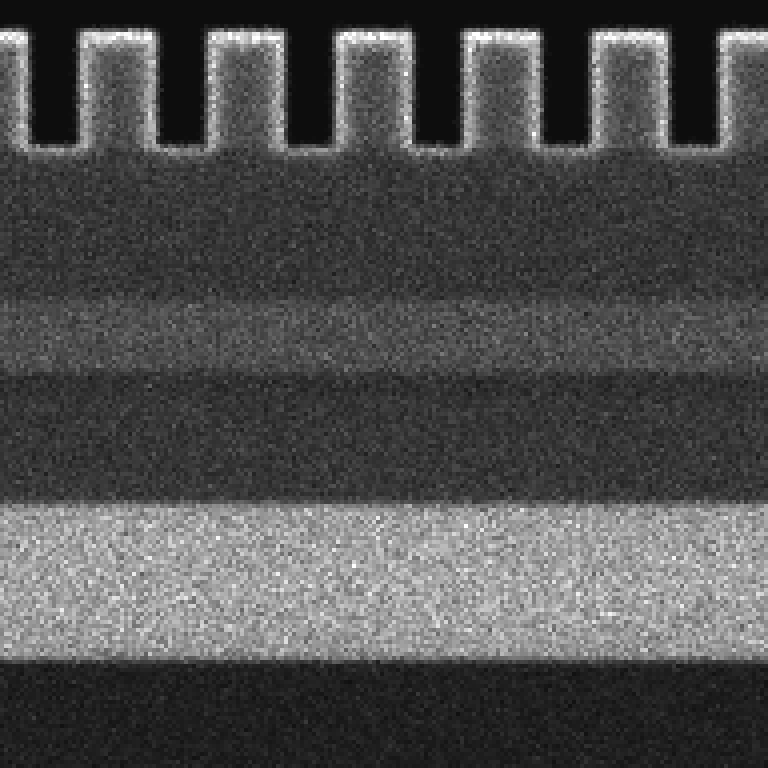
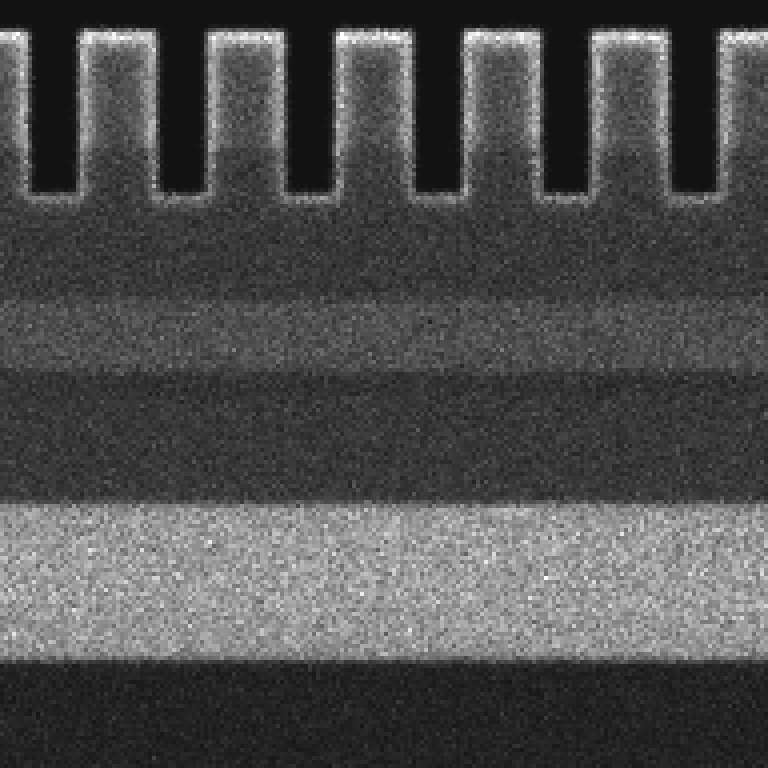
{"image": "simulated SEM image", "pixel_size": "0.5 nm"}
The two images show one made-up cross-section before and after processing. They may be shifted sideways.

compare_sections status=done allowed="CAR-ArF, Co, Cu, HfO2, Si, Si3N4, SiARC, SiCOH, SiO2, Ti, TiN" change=removed material="TiN"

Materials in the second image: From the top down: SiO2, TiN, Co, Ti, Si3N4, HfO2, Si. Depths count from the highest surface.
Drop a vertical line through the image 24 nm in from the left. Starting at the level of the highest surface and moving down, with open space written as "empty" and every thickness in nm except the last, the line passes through empty 82, TiN 52, Co 36, Ti 12, Si3N4 54, HfO2 78, Si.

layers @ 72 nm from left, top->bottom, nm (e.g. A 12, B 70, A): SiO2 58, TiN 76, Co 36, Ti 12, Si3N4 54, HfO2 78, Si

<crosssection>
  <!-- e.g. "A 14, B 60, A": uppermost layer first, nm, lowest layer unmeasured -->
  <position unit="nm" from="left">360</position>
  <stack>SiO2 58, TiN 76, Co 36, Ti 12, Si3N4 54, HfO2 78, Si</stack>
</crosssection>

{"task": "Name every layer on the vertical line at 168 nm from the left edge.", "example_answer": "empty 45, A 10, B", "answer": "SiO2 58, TiN 76, Co 36, Ti 12, Si3N4 54, HfO2 78, Si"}